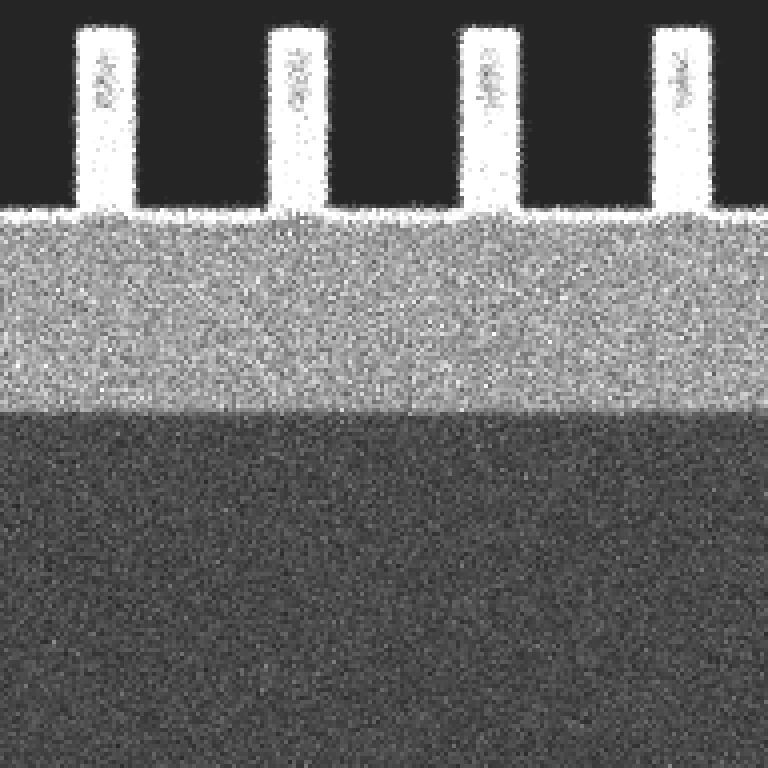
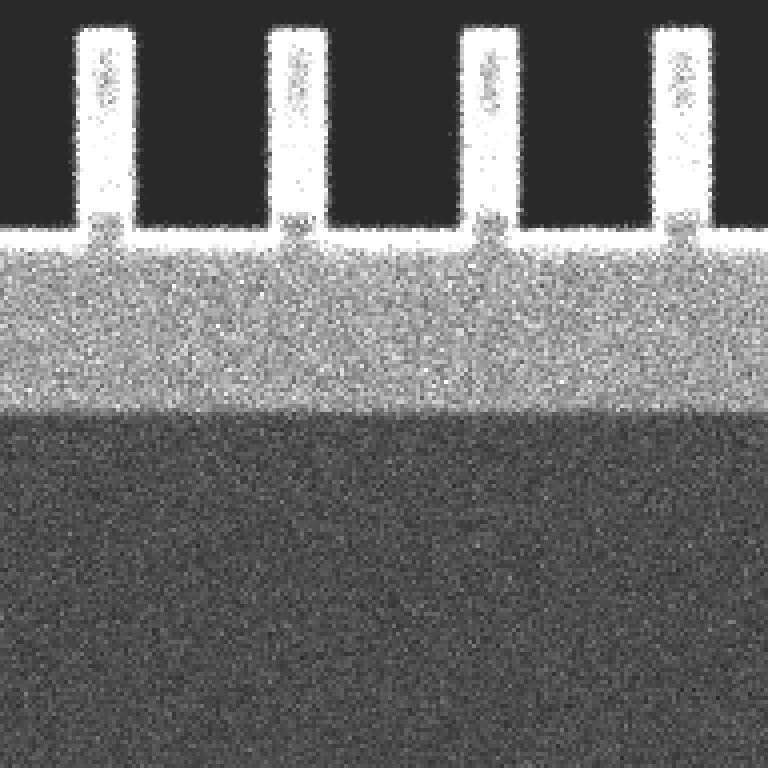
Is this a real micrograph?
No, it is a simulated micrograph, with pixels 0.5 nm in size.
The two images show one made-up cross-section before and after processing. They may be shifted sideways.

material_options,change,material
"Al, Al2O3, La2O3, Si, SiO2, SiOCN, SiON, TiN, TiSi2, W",removed,TiN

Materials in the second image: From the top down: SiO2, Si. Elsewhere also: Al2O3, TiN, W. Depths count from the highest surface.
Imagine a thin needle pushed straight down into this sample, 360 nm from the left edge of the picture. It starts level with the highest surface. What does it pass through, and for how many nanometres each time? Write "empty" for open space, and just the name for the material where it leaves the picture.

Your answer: empty 100, SiO2 90, Si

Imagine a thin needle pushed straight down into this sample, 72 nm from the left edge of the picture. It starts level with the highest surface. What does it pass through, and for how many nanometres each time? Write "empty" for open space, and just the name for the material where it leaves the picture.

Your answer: empty 100, SiO2 90, Si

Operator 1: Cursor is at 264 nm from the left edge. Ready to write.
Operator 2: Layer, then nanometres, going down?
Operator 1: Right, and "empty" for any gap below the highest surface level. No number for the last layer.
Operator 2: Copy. empty 100, SiO2 90, Si